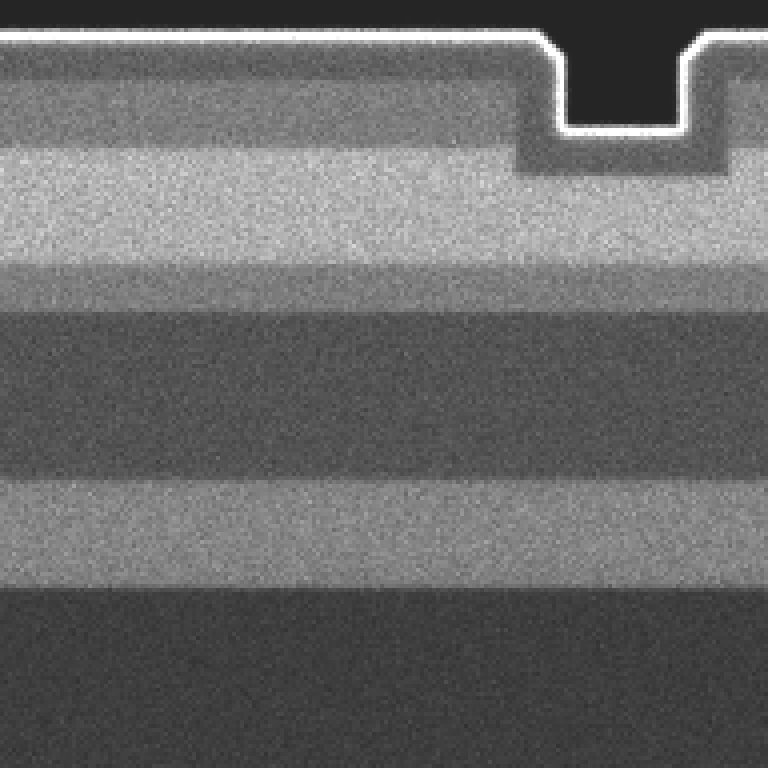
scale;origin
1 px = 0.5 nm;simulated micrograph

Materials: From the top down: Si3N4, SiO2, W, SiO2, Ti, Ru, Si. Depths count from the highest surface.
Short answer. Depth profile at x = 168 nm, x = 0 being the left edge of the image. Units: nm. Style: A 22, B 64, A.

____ Si3N4 24, SiO2 34, W 58, SiO2 24, Ti 84, Ru 54, Si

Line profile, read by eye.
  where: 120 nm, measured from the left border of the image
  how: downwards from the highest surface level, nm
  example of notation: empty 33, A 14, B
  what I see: Si3N4 24, SiO2 34, W 58, SiO2 24, Ti 84, Ru 54, Si